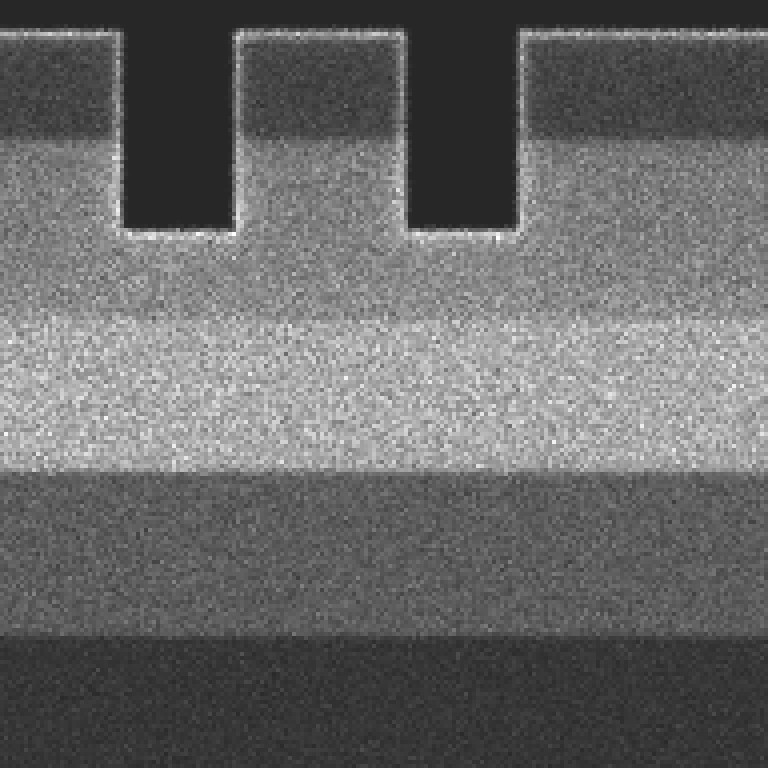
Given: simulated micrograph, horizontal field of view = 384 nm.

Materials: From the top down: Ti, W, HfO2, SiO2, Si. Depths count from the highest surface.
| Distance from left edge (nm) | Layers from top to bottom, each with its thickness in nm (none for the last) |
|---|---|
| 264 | Ti 54, W 90, HfO2 76, SiO2 82, Si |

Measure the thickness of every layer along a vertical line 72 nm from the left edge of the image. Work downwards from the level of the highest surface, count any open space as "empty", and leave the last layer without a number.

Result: empty 100, W 44, HfO2 76, SiO2 82, Si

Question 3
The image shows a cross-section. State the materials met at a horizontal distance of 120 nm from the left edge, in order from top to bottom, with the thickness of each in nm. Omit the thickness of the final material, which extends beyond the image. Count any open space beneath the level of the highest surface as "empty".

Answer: Ti 54, W 90, HfO2 76, SiO2 82, Si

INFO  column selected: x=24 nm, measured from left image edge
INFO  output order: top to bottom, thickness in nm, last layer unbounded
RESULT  Ti 54, W 90, HfO2 76, SiO2 82, Si